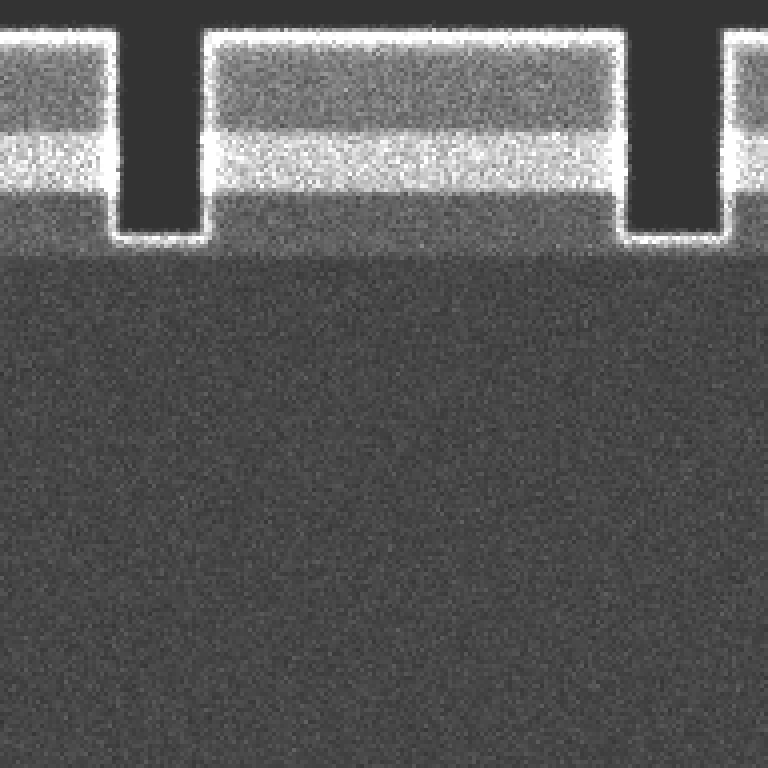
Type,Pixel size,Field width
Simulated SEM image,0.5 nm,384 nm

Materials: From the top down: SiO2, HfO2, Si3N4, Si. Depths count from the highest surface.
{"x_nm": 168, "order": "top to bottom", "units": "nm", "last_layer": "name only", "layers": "SiO2 50, HfO2 30, Si3N4 32, Si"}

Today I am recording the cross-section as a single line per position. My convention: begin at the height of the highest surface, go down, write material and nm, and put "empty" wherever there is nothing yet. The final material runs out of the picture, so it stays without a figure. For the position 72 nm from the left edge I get empty 102, Si3N4 10, Si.